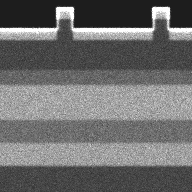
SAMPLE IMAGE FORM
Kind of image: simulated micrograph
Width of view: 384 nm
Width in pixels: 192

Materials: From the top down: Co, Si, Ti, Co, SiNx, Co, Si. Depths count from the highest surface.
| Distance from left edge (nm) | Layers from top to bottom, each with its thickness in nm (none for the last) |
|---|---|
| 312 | Co 22, Si 102, Ti 30, Co 70, SiNx 46, Co 46, Si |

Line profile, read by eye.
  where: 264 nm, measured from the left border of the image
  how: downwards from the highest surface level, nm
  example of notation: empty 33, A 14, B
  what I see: empty 42, Co 22, Si 60, Ti 30, Co 70, SiNx 46, Co 46, Si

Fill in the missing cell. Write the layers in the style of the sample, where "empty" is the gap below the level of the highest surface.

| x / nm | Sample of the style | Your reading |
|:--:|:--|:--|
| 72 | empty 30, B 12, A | empty 42, Co 22, Si 60, Ti 30, Co 70, SiNx 46, Co 46, Si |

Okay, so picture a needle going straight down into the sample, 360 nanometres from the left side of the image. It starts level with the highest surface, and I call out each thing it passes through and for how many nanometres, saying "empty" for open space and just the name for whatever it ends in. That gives empty 42, Co 22, Si 60, Ti 30, Co 70, SiNx 46, Co 46, Si